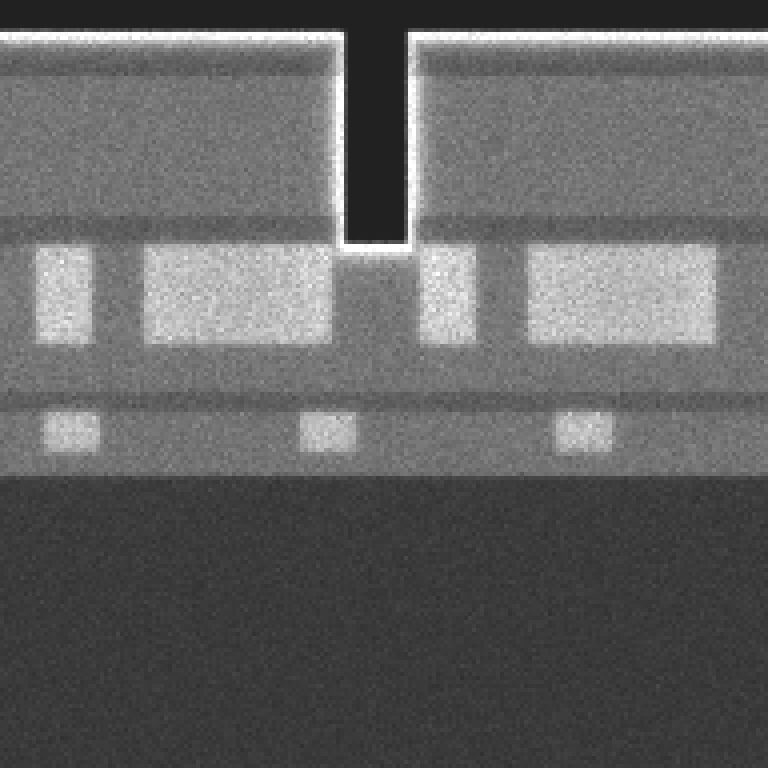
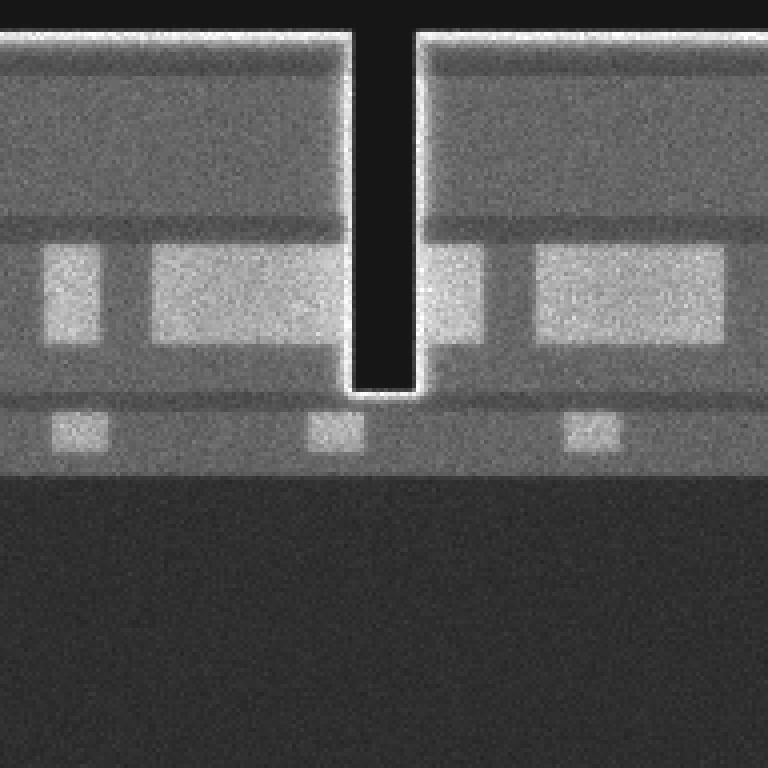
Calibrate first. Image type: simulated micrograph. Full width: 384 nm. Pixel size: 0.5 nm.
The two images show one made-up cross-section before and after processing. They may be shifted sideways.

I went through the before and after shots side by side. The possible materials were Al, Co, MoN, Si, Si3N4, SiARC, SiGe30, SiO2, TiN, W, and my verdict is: removed, SiO2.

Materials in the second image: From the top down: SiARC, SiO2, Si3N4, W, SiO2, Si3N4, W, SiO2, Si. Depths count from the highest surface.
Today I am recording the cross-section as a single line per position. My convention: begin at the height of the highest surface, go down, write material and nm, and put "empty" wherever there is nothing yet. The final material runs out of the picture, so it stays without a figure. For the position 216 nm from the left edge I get SiARC 22, SiO2 70, Si3N4 14, W 50, SiO2 24, Si3N4 10, SiO2 32, Si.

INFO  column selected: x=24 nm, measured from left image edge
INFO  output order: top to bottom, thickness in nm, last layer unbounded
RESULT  SiARC 22, SiO2 70, Si3N4 14, W 50, SiO2 24, Si3N4 10, SiO2 32, Si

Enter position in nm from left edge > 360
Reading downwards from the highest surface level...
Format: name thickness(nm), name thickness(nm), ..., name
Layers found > SiARC 22, SiO2 70, Si3N4 14, W 50, SiO2 24, Si3N4 10, SiO2 32, Si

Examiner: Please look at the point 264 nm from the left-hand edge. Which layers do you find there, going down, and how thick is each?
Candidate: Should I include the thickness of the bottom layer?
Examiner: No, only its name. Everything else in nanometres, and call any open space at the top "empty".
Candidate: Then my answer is SiARC 22, SiO2 70, Si3N4 14, SiO2 74, Si3N4 10, SiO2 32, Si